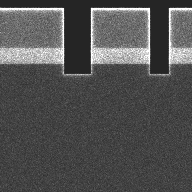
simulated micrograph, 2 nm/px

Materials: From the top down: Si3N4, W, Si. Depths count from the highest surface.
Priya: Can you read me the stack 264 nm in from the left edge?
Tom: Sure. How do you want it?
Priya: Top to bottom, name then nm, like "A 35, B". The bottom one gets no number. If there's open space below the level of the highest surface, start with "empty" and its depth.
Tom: Si3N4 80, W 32, Si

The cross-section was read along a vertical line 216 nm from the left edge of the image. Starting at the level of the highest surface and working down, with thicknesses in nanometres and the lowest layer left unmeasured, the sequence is Si3N4 80, W 32, Si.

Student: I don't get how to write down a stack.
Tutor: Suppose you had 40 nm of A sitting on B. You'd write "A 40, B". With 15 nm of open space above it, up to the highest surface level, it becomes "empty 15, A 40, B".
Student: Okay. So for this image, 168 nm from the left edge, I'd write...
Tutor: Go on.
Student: empty 132, Si